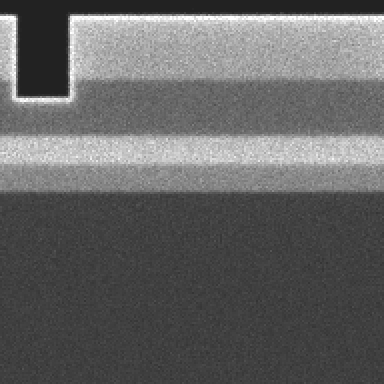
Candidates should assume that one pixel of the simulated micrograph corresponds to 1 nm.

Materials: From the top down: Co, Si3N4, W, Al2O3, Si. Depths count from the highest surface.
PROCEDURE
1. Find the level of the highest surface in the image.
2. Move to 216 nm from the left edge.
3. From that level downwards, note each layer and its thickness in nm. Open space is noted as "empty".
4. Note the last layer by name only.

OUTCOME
Co 64, Si3N4 56, W 28, Al2O3 28, Si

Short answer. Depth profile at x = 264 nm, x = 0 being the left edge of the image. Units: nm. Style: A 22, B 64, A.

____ Co 64, Si3N4 56, W 28, Al2O3 28, Si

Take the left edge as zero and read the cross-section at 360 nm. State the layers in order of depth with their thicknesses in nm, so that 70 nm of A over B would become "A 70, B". Co 64, Si3N4 56, W 28, Al2O3 28, Si